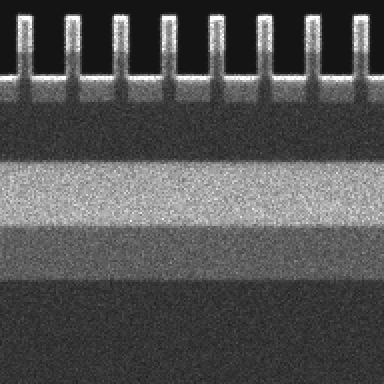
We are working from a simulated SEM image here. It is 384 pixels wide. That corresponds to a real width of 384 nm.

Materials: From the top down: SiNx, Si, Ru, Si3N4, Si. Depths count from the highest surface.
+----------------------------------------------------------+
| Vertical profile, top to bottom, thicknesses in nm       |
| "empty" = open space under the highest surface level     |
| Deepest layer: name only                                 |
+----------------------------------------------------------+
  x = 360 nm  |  SiNx 36, Si 110, Ru 64, Si3N4 54, Si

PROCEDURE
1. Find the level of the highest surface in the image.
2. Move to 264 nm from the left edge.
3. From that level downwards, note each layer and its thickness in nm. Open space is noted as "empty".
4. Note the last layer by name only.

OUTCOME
SiNx 36, Si 110, Ru 64, Si3N4 54, Si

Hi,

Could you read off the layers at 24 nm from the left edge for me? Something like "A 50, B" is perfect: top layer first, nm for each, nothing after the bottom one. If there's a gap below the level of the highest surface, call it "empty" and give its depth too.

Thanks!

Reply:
SiNx 36, Si 110, Ru 64, Si3N4 54, Si